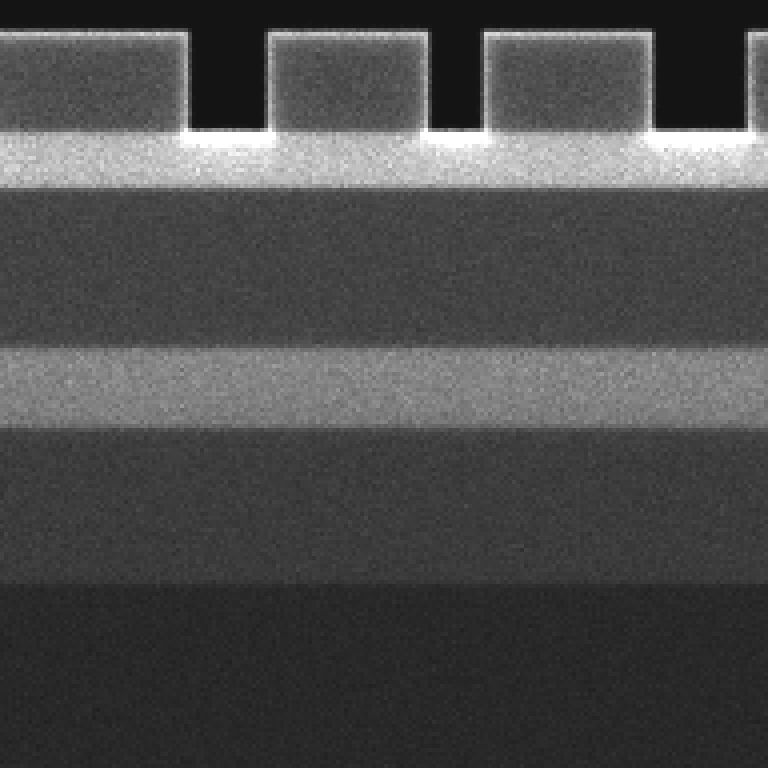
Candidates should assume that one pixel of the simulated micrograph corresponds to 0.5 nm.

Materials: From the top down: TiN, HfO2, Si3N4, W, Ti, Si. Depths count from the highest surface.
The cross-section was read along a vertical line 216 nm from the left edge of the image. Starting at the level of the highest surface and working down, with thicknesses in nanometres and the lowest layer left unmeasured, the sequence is empty 50, HfO2 28, Si3N4 80, W 40, Ti 78, Si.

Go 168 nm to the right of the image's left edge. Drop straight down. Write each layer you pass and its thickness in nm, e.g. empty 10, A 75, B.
TiN 50, HfO2 28, Si3N4 80, W 40, Ti 78, Si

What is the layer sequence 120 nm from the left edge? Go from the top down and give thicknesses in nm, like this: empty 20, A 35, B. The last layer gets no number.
empty 50, HfO2 28, Si3N4 80, W 40, Ti 78, Si